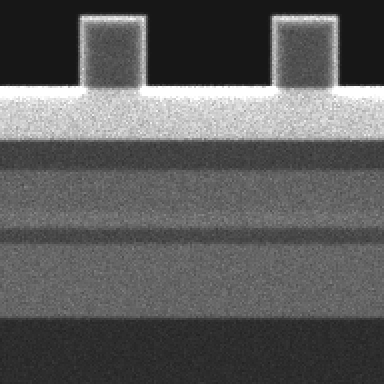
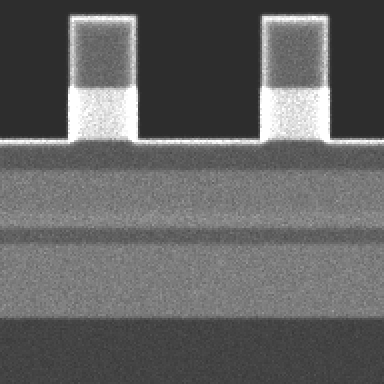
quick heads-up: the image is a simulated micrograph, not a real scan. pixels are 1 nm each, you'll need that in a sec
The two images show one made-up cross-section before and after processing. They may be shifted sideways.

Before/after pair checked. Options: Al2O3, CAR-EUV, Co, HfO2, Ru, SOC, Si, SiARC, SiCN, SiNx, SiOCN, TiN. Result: removed HfO2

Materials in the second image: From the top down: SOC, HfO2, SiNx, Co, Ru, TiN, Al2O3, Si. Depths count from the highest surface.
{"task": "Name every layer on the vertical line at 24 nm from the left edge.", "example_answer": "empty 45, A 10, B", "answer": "empty 124, SiNx 30, Co 42, Ru 16, TiN 16, Al2O3 74, Si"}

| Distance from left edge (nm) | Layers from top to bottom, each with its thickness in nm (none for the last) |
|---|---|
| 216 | empty 124, SiNx 30, Co 42, Ru 16, TiN 16, Al2O3 74, Si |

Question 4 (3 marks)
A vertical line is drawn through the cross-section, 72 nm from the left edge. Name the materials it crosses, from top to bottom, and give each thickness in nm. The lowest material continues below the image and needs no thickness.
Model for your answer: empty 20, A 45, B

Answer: SOC 72, HfO2 52, SiNx 30, Co 42, Ru 16, TiN 16, Al2O3 74, Si